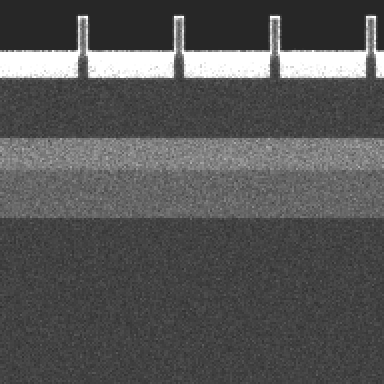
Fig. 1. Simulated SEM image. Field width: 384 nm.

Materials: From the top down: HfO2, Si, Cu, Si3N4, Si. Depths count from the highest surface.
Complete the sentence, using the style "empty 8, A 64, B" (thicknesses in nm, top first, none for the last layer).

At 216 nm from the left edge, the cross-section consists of empty 36, HfO2 26, Si 60, Cu 32, Si3N4 48, Si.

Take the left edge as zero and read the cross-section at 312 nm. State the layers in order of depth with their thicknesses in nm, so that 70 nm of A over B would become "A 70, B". empty 36, HfO2 26, Si 60, Cu 32, Si3N4 48, Si